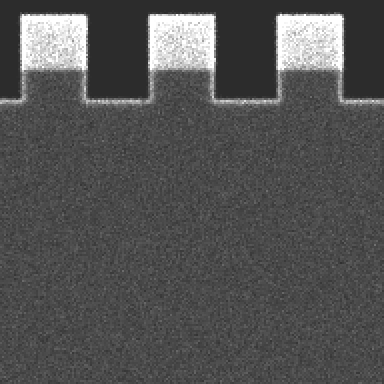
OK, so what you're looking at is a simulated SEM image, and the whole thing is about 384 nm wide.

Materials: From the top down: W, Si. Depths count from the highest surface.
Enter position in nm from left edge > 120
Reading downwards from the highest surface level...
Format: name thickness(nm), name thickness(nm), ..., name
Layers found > empty 84, Si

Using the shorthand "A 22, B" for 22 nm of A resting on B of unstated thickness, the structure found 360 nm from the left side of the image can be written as empty 84, Si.